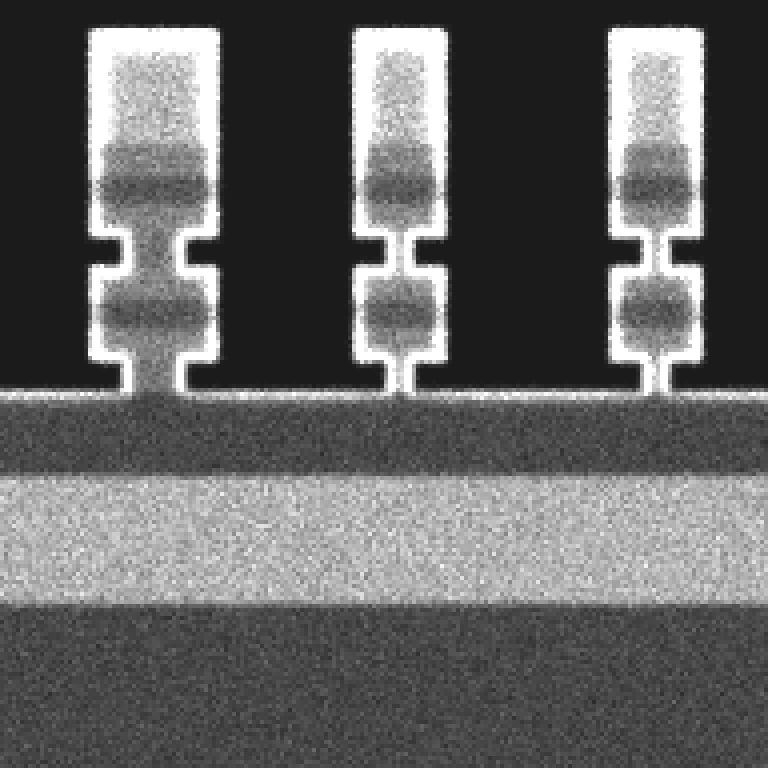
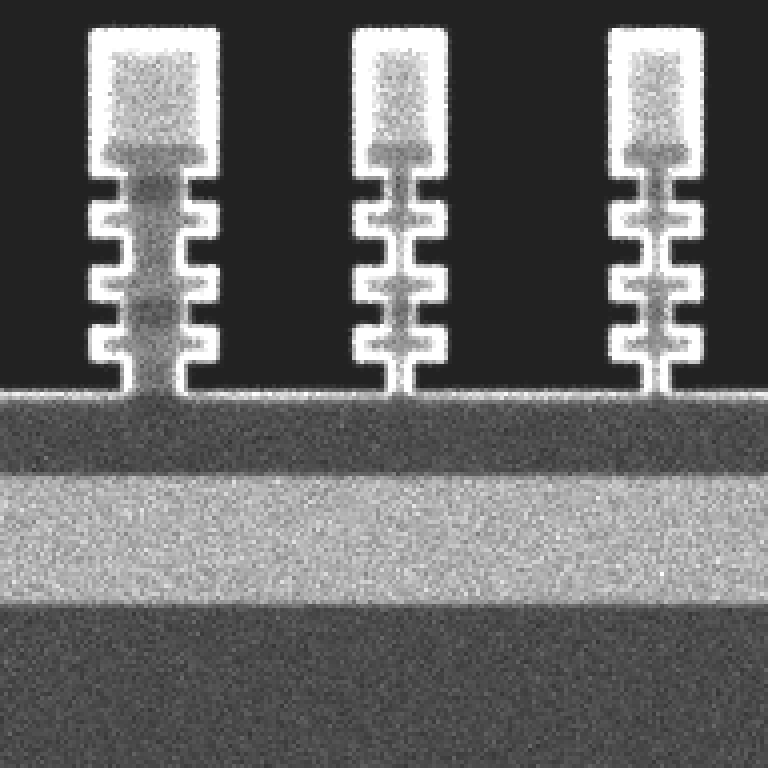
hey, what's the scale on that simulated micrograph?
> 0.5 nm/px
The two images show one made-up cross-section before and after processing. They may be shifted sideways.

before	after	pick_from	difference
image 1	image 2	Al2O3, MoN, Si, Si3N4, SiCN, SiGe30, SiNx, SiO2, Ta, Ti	SiGe30 removed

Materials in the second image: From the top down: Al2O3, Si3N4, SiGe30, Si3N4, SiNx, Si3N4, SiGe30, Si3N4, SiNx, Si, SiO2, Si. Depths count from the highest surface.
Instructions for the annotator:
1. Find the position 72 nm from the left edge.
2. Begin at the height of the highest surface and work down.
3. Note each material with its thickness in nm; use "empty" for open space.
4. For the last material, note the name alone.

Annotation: Al2O3 56, Si3N4 16, SiGe30 14, Si3N4 16, SiNx 16, Si3N4 16, SiGe30 14, Si3N4 16, SiNx 16, Si 42, SiO2 64, Si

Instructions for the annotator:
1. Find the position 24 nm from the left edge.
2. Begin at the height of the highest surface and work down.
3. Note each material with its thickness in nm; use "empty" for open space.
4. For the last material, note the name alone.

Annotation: empty 180, Si 42, SiO2 64, Si